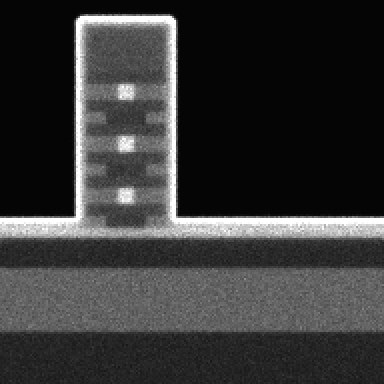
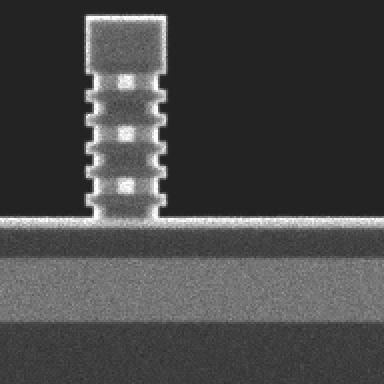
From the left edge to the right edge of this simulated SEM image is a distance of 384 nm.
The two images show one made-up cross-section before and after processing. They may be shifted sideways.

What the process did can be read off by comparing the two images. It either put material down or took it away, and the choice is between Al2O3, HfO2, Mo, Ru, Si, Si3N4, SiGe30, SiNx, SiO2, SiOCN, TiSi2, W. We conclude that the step removed Al2O3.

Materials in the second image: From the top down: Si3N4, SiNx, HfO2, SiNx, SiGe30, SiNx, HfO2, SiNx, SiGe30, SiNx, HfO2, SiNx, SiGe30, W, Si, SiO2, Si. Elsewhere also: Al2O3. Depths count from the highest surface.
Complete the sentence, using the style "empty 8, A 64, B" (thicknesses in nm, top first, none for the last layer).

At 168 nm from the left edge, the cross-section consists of empty 202, W 10, Si 30, SiO2 64, Si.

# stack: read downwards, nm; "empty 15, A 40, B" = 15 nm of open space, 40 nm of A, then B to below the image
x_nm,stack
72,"empty 202, W 10, Si 30, SiO2 64, Si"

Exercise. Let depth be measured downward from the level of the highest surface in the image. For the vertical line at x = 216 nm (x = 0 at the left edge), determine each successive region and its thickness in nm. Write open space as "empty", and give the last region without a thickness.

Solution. empty 202, W 10, Si 30, SiO2 64, Si